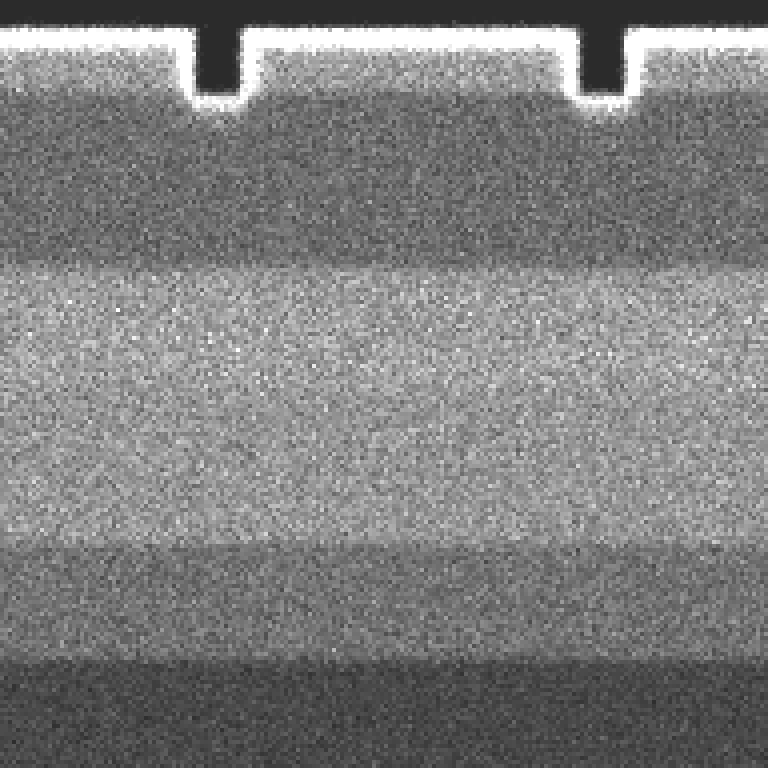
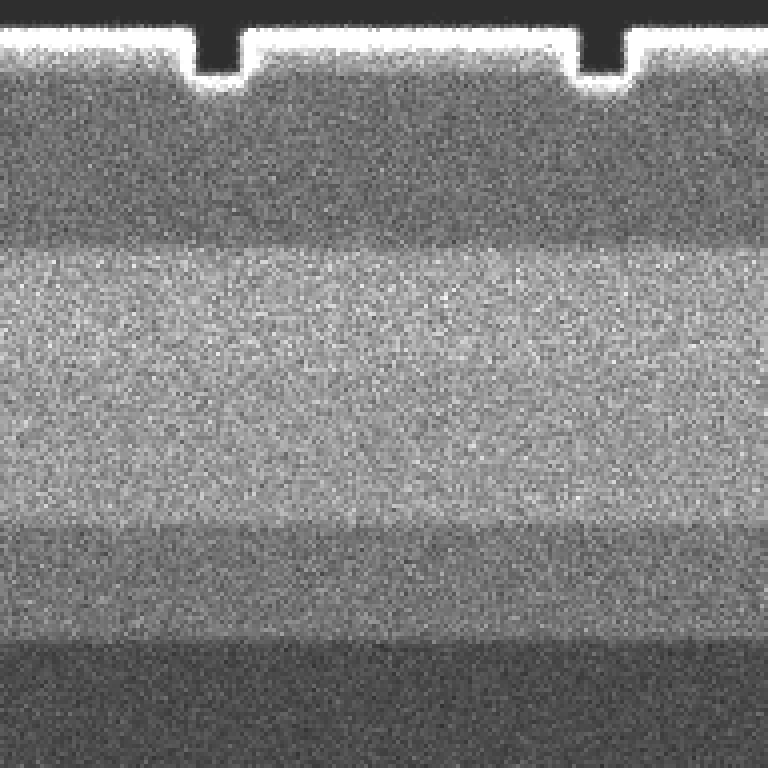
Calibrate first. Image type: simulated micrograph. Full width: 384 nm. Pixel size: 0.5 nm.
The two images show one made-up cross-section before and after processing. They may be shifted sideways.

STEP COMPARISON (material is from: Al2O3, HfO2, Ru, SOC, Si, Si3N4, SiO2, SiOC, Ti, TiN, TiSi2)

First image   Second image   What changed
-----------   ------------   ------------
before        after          Al2O3, removed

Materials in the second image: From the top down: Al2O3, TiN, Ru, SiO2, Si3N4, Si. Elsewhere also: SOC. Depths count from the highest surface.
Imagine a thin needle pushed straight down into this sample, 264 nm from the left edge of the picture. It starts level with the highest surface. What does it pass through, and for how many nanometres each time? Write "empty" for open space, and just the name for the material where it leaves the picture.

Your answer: Al2O3 20, TiN 88, Ru 60, SiO2 78, Si3N4 58, Si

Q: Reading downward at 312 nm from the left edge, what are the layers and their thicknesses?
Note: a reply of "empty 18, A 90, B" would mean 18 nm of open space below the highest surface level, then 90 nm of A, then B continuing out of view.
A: empty 22, SOC 10, TiN 76, Ru 60, SiO2 78, Si3N4 58, Si